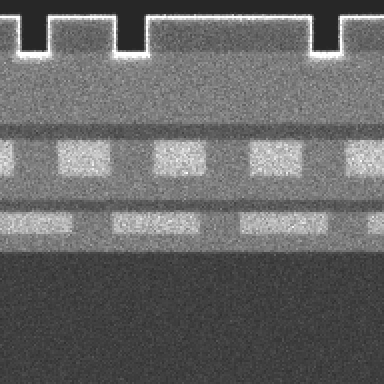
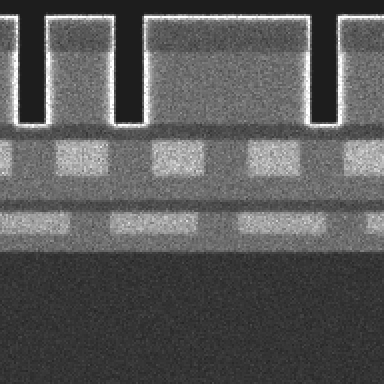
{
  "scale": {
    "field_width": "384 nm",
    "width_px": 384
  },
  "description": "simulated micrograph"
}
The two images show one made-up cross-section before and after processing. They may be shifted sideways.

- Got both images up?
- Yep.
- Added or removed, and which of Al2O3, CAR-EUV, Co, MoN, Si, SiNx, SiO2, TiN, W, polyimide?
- removed, SiO2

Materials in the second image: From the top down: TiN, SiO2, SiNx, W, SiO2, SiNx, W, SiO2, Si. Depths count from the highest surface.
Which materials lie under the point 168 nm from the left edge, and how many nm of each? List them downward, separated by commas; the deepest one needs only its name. TiN 36, SiO2 72, SiNx 16, W 36, SiO2 24, SiNx 12, W 22, SiO2 18, Si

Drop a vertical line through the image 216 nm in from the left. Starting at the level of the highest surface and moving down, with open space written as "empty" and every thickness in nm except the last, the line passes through TiN 36, SiO2 72, SiNx 16, SiO2 60, SiNx 12, SiO2 40, Si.